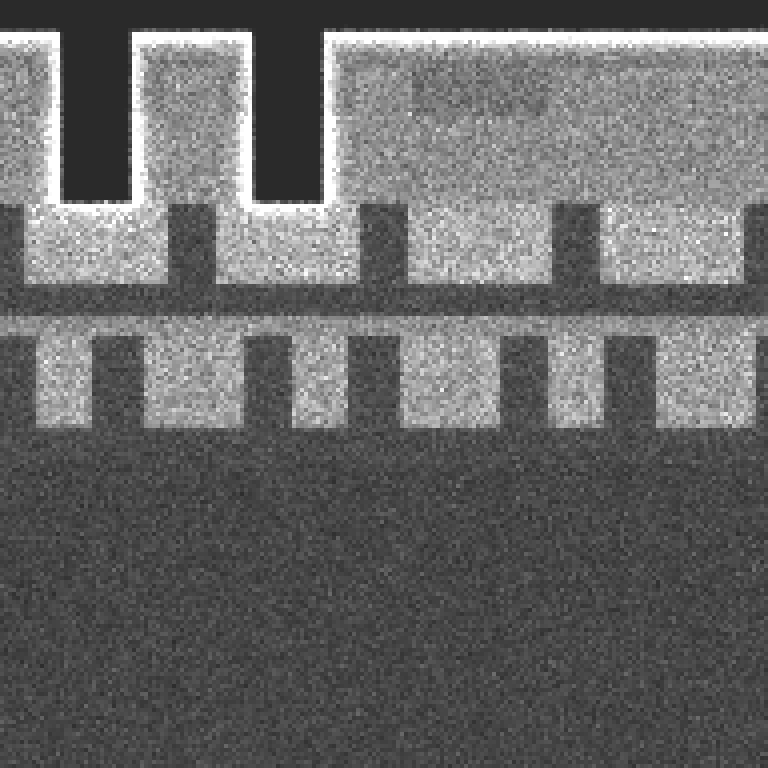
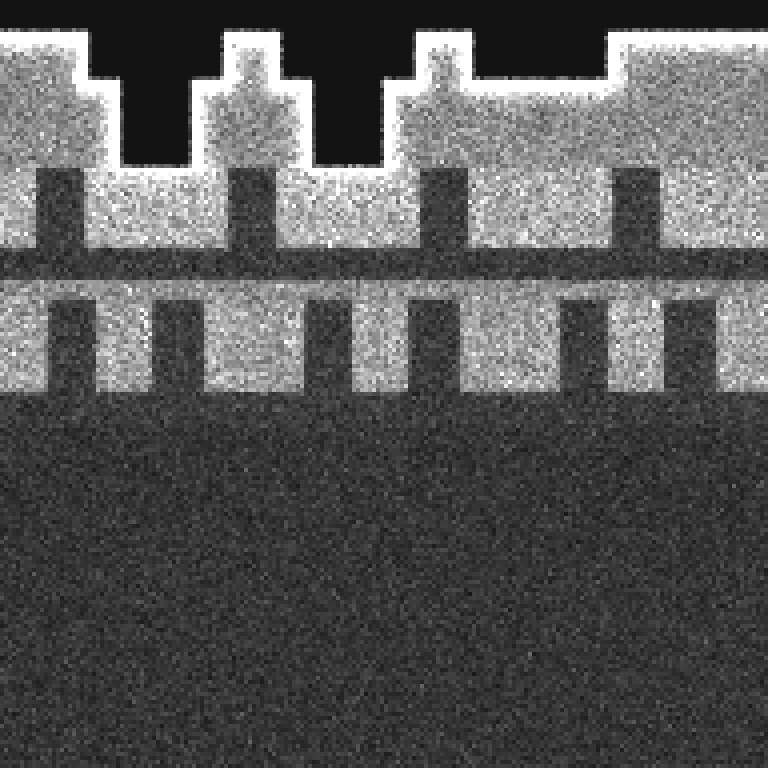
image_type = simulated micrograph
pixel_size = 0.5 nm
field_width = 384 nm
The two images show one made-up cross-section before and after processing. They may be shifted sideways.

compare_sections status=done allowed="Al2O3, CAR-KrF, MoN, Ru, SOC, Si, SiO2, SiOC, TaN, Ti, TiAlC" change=removed material="SOC"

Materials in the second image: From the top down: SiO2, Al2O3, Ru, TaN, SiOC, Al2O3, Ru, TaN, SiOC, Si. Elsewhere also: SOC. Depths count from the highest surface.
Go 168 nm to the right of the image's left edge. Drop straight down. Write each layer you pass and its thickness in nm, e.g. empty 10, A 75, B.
empty 68, Ru 30, TaN 10, SiOC 16, Al2O3 10, SiOC 64, Si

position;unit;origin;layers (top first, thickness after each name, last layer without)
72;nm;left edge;empty 68, Ru 30, TaN 10, SiOC 16, Al2O3 10, TaN 46, SiOC 18, Si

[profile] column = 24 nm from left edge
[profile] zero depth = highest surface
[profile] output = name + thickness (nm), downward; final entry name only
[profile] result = SiO2 54, Al2O3 14, SiOC 56, Al2O3 10, SiOC 64, Si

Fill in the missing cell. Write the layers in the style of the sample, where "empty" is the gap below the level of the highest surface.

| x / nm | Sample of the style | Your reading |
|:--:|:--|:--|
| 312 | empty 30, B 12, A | SiO2 54, Al2O3 14, SiOC 56, Al2O3 10, TaN 46, SiOC 18, Si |